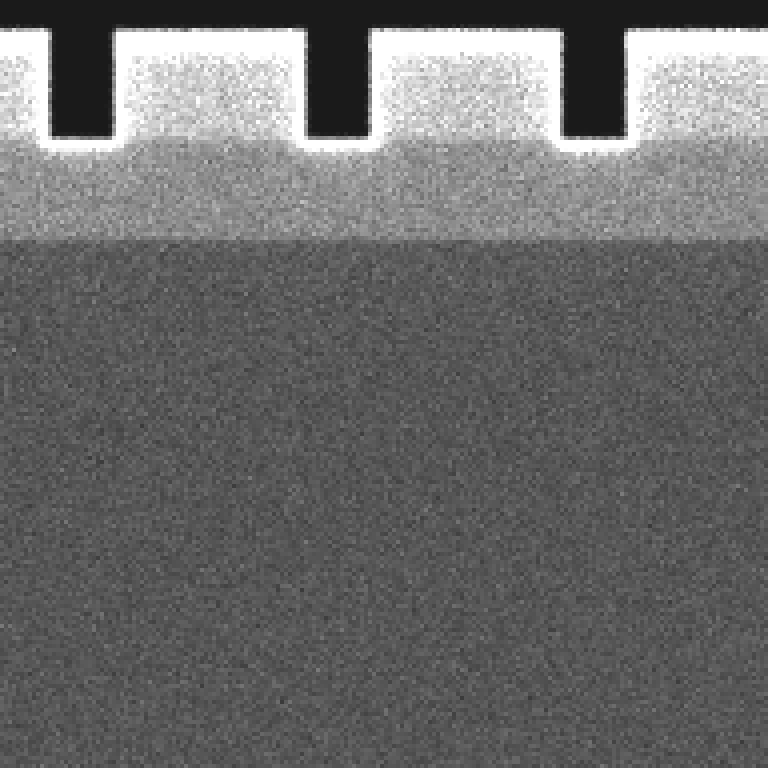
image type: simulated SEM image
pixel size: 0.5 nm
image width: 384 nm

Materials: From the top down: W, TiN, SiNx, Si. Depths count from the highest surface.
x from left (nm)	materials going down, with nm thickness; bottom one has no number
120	W 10, TiN 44, SiNx 50, Si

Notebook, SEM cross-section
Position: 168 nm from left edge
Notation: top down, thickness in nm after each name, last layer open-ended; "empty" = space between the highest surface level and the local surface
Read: empty 54, SiNx 50, Si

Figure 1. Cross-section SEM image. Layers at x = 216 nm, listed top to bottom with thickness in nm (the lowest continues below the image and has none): W 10, TiN 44, SiNx 50, Si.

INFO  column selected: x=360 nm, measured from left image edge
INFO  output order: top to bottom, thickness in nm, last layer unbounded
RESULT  W 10, TiN 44, SiNx 50, Si